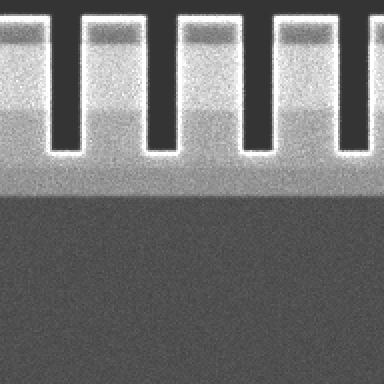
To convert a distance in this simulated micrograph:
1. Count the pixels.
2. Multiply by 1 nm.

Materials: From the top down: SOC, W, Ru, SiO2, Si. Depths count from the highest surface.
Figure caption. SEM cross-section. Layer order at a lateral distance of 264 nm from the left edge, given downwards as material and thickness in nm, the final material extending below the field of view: empty 136, Ru 16, SiO2 28, Si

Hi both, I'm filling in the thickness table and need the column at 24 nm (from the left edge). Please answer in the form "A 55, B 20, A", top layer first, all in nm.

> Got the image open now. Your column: SOC 28, W 66, Ru 58, SiO2 28, Si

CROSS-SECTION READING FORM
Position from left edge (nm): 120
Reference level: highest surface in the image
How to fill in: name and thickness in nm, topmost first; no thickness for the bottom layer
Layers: SOC 28, W 66, Ru 58, SiO2 28, Si